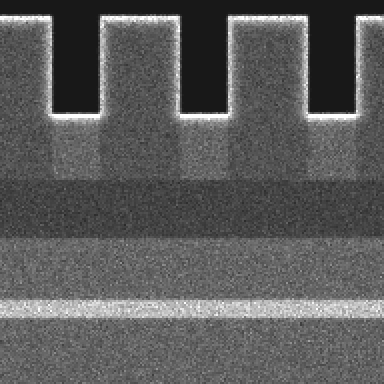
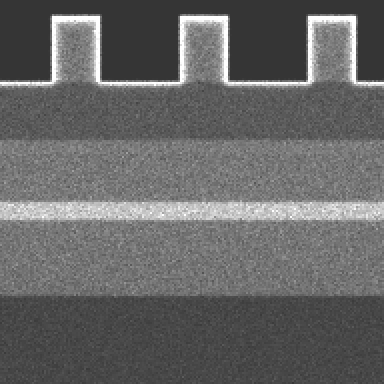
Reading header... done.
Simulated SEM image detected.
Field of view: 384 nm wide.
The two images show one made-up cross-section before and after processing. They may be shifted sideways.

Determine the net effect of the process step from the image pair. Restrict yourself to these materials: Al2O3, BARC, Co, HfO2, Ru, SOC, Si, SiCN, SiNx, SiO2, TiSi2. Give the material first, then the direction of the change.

SOC: removed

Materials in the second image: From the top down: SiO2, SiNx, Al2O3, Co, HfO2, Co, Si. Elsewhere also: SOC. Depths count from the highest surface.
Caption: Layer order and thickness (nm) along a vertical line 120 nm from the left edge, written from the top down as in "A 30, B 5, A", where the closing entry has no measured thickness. empty 66, SiNx 58, Al2O3 14, Co 48, HfO2 18, Co 76, Si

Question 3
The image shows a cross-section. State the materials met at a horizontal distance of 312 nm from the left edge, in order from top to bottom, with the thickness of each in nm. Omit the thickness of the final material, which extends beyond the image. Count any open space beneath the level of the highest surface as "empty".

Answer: SiO2 66, SiNx 58, Al2O3 14, Co 48, HfO2 18, Co 76, Si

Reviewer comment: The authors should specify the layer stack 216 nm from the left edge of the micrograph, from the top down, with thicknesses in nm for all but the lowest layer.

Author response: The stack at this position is SiO2 66, SiNx 58, Al2O3 14, Co 48, HfO2 18, Co 76, Si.